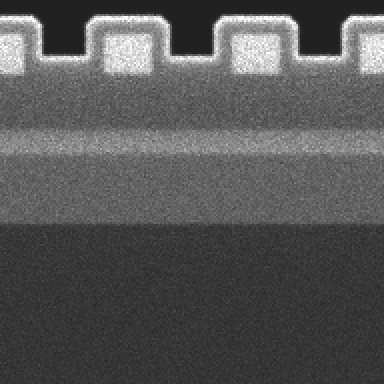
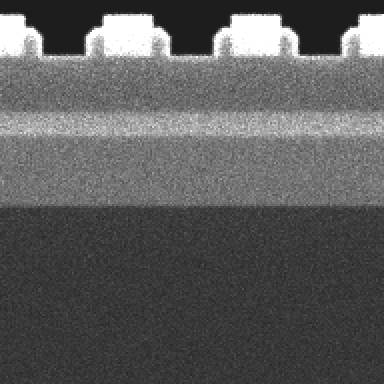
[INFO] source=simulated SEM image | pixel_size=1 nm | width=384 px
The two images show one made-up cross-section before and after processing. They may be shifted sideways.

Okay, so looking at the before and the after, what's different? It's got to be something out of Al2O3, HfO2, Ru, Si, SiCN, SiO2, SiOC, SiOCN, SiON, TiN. Al2O3, removed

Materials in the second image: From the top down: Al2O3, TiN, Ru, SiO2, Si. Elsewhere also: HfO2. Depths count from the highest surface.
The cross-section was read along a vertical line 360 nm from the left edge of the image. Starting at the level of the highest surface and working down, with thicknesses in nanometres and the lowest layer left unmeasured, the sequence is HfO2 40, TiN 56, Ru 24, SiO2 70, Si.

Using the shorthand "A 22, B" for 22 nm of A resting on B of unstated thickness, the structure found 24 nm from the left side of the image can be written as empty 12, Al2O3 28, TiN 56, Ru 24, SiO2 70, Si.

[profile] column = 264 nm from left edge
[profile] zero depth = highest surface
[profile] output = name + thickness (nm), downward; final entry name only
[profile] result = HfO2 40, TiN 56, Ru 24, SiO2 70, Si